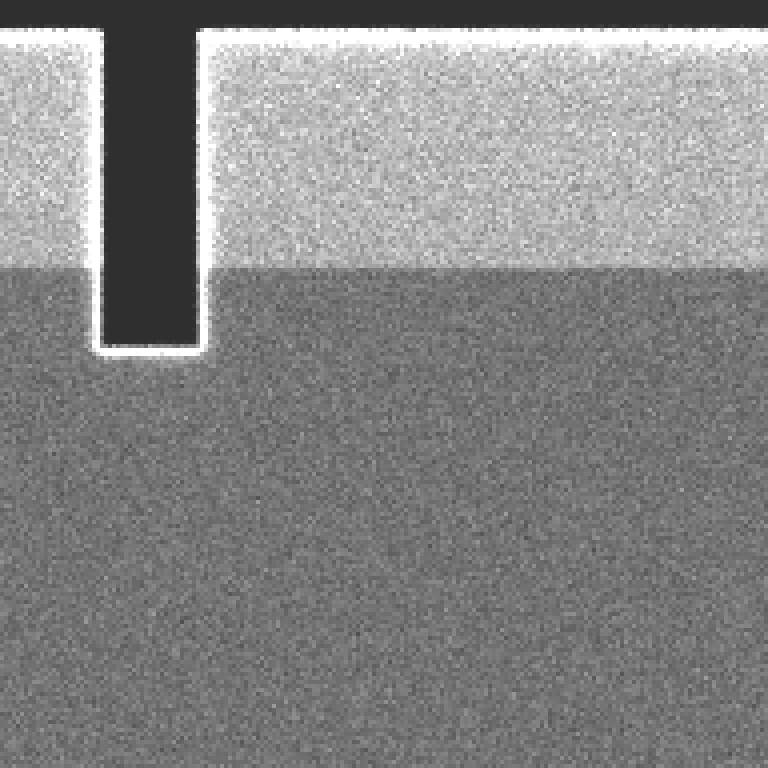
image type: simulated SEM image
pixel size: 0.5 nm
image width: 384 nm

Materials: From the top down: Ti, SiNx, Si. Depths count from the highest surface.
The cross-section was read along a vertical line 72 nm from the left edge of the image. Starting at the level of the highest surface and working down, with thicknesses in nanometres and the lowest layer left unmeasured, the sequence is empty 158, Si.